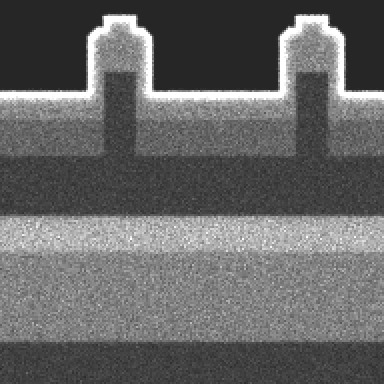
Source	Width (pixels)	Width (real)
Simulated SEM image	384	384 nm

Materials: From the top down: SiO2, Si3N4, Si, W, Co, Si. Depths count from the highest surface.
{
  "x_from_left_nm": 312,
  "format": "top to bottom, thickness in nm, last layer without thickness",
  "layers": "SiO2 56, Si 144, W 36, Co 90, Si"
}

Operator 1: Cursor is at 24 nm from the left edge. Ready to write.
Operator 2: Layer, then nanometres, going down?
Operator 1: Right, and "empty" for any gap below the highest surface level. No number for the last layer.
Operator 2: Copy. empty 76, SiO2 28, Si3N4 36, Si 60, W 36, Co 90, Si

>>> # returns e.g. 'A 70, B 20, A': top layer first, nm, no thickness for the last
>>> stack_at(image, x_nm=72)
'empty 76, SiO2 28, Si3N4 36, Si 60, W 36, Co 90, Si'